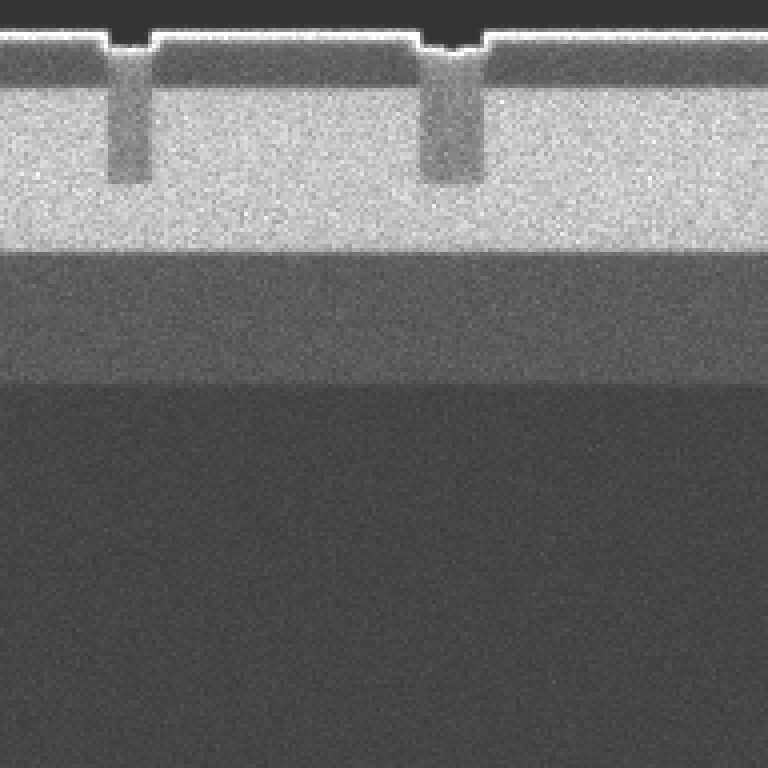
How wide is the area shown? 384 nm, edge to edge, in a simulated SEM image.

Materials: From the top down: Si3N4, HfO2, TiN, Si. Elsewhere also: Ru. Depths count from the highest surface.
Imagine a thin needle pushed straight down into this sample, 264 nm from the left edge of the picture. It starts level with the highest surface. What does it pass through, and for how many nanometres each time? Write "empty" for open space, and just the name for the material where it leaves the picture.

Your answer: Si3N4 28, HfO2 82, TiN 66, Si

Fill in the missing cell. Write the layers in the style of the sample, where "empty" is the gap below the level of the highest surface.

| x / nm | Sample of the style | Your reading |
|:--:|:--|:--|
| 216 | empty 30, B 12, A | empty 8, Ru 68, HfO2 34, TiN 66, Si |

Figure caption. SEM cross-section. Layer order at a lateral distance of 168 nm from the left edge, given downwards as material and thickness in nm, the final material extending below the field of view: Si3N4 28, HfO2 82, TiN 66, Si